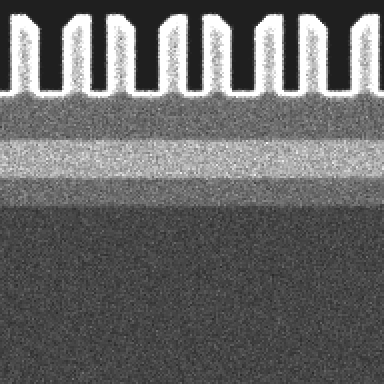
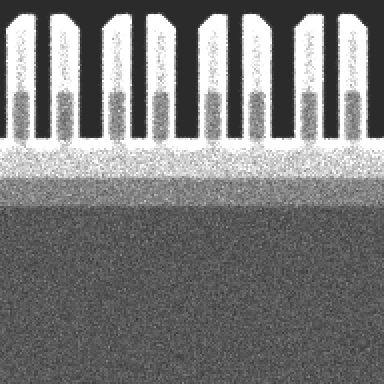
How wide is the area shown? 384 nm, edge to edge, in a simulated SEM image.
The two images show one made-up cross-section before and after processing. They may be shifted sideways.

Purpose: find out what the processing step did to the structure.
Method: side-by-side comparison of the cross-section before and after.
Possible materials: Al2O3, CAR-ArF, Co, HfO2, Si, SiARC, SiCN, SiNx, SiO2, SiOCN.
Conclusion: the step removed SiOCN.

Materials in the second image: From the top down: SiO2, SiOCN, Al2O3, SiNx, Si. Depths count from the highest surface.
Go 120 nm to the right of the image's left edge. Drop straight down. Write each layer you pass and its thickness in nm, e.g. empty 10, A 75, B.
SiO2 76, SiOCN 48, Al2O3 38, SiNx 28, Si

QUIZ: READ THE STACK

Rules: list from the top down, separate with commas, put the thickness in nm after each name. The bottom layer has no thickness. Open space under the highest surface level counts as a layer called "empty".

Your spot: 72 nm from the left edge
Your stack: empty 8, SiO2 68, SiOCN 48, Al2O3 38, SiNx 28, Si